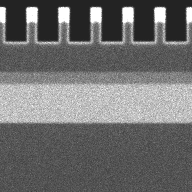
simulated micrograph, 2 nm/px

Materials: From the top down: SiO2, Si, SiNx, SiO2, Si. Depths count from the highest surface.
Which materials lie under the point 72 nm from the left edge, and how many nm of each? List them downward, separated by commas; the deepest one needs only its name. SiO2 28, Si 100, SiNx 24, SiO2 78, Si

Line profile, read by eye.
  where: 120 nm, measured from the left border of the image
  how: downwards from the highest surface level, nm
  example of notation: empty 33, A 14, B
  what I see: SiO2 28, Si 100, SiNx 24, SiO2 78, Si